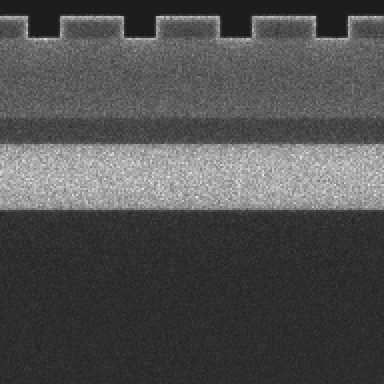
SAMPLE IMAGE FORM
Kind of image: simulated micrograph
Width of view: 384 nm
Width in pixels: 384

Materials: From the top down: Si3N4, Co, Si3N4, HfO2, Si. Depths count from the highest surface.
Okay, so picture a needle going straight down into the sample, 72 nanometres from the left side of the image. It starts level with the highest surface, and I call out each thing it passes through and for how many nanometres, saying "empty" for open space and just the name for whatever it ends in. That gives Si3N4 22, Co 80, Si3N4 26, HfO2 66, Si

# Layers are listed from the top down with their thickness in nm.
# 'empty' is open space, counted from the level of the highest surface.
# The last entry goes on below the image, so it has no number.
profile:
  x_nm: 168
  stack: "Si3N4 22, Co 80, Si3N4 26, HfO2 66, Si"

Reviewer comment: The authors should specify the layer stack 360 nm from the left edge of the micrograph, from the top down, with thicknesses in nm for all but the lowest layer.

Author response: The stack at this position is Si3N4 22, Co 80, Si3N4 26, HfO2 66, Si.